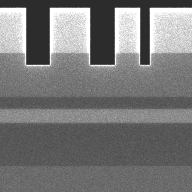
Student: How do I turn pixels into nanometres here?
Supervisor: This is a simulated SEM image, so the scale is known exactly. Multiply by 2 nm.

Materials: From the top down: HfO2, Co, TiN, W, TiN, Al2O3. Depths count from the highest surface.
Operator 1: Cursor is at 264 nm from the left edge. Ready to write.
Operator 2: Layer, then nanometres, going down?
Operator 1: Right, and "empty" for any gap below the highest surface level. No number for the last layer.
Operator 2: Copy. HfO2 90, Co 88, TiN 24, W 28, TiN 86, Al2O3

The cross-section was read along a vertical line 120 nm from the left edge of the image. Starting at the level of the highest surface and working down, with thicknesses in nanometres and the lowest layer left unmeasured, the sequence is HfO2 90, Co 88, TiN 24, W 28, TiN 86, Al2O3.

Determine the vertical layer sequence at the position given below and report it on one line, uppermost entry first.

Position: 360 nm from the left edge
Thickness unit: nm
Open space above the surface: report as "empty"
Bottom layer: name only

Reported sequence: HfO2 90, Co 88, TiN 24, W 28, TiN 86, Al2O3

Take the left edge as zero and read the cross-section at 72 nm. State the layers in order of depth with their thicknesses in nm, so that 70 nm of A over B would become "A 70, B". empty 114, Co 64, TiN 24, W 28, TiN 86, Al2O3